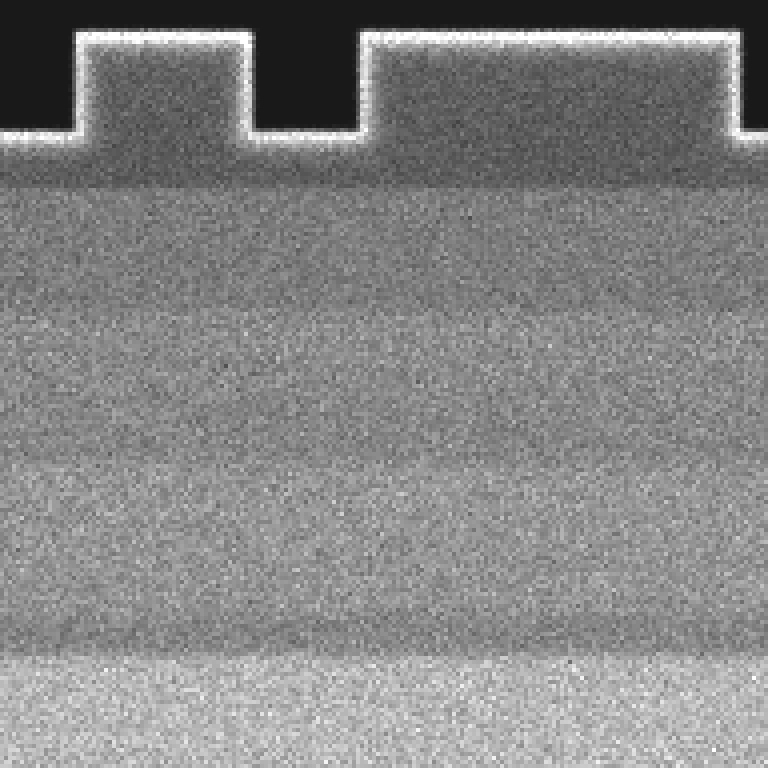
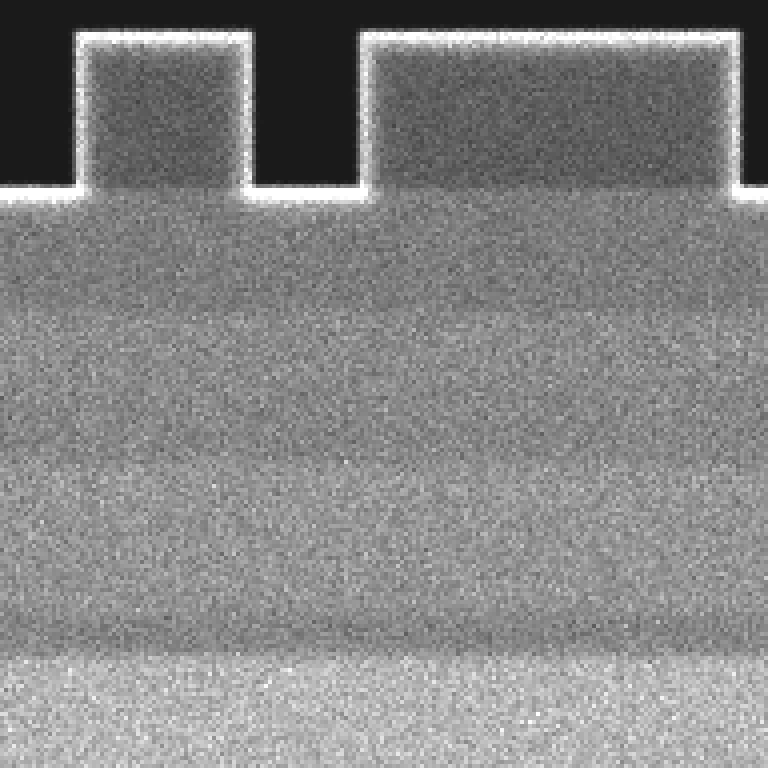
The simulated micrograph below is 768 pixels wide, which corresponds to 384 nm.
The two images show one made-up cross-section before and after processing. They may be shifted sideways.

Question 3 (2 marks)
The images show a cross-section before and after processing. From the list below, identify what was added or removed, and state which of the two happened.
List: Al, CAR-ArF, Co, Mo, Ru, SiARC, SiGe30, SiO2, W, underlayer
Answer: underlayer was removed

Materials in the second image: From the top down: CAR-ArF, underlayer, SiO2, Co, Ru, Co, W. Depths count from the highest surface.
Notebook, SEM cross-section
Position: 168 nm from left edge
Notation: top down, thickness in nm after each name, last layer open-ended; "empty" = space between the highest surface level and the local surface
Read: empty 78, SiO2 62, Co 76, Ru 76, Co 20, W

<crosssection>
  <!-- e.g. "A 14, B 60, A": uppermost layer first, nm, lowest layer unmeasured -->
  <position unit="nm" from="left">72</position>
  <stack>CAR-ArF 50, underlayer 28, SiO2 62, Co 76, Ru 76, Co 20, W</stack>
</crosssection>